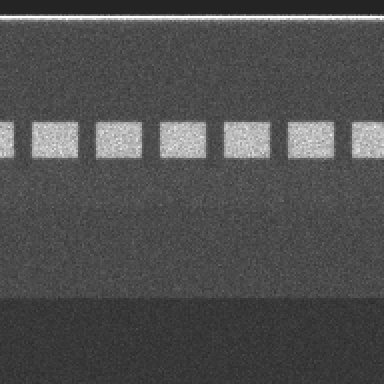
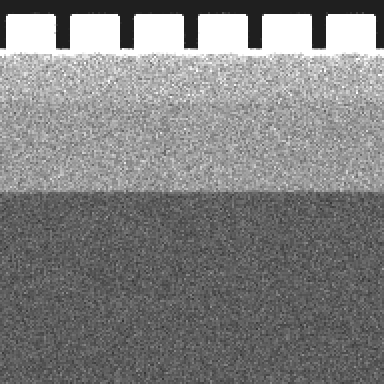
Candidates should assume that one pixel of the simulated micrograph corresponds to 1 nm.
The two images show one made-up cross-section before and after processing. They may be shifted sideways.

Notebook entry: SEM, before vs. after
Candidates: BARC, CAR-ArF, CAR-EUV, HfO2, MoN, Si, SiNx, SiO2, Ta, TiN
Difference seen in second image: SiNx removed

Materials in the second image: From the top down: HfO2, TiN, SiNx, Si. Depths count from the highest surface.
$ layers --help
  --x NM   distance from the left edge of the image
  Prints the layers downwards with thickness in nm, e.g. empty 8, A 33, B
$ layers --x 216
HfO2 36, TiN 50, SiNx 90, Si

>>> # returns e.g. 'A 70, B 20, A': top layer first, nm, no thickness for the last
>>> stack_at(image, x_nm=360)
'HfO2 36, TiN 50, SiNx 90, Si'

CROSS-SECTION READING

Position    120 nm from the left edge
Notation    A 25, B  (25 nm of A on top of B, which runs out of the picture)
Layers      empty 34, SiNx 12, TiN 40, SiNx 90, Si